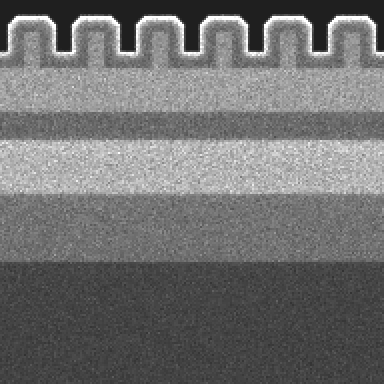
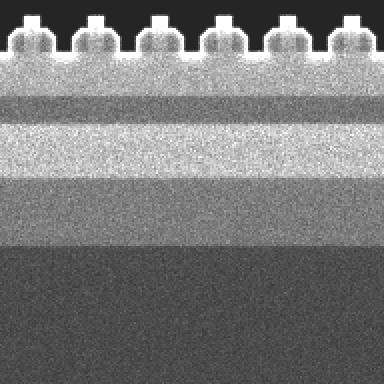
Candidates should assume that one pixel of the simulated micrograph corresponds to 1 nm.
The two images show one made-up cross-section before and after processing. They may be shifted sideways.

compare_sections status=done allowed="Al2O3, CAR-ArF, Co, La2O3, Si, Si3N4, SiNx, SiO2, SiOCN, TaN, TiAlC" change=removed material="SiOCN"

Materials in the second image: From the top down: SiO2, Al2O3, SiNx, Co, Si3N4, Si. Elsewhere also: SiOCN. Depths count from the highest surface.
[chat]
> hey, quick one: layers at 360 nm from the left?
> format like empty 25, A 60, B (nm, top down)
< empty 12, SiOCN 24, Al2O3 44, SiNx 28, Co 54, Si3N4 68, Si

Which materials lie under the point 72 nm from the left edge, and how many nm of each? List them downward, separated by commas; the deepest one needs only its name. empty 20, SiOCN 16, Al2O3 44, SiNx 28, Co 54, Si3N4 68, Si